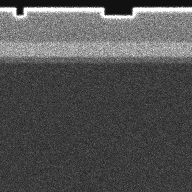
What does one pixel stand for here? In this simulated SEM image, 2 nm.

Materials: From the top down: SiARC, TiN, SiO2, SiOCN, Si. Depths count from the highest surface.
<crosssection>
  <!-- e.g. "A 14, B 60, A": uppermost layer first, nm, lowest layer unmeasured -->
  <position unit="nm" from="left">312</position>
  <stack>SiARC 16, TiN 52, SiO2 30, SiOCN 12, Si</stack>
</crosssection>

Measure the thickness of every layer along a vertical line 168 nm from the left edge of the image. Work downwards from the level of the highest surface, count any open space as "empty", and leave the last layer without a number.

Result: SiARC 16, TiN 52, SiO2 30, SiOCN 12, Si